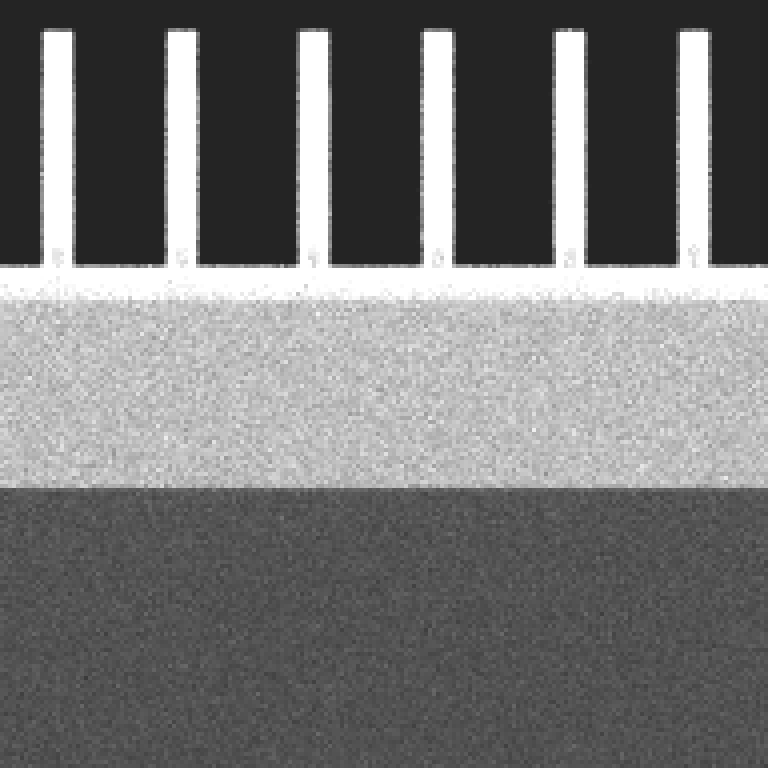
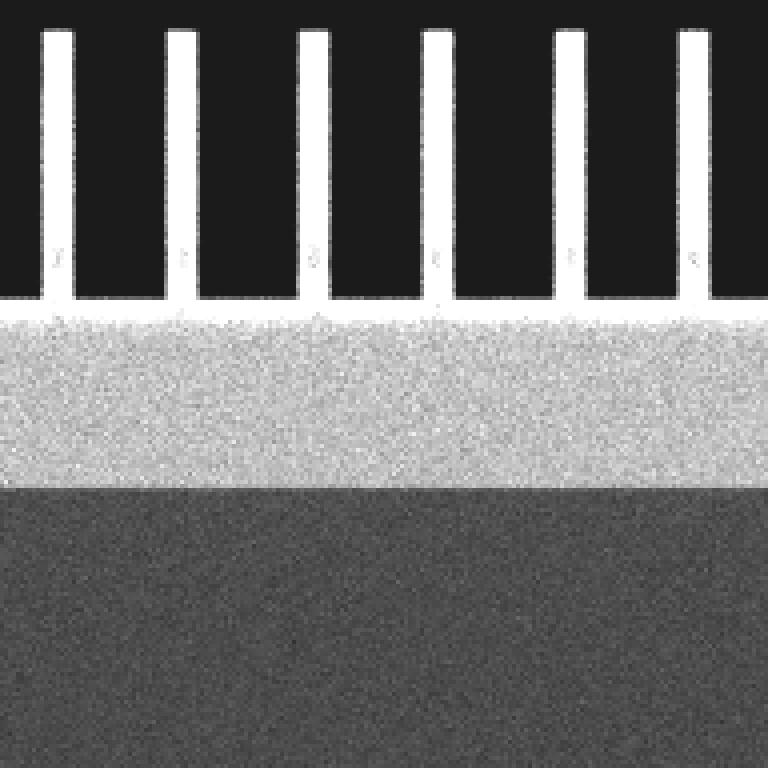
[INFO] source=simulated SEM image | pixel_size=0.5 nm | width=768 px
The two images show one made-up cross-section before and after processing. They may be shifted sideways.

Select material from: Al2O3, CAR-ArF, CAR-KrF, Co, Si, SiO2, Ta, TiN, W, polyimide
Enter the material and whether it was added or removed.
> Co / removed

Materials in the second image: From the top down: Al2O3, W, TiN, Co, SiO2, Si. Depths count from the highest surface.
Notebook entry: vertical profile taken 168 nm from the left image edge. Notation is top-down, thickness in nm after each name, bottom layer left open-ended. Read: empty 134, SiO2 94, Si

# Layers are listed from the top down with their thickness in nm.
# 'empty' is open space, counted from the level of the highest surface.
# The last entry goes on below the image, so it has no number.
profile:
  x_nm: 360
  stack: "empty 134, SiO2 94, Si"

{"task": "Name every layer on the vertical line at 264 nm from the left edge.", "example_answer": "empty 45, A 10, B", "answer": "empty 134, SiO2 94, Si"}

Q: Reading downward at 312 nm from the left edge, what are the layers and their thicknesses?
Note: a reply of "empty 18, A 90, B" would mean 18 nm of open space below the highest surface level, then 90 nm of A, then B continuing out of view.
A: empty 134, SiO2 94, Si